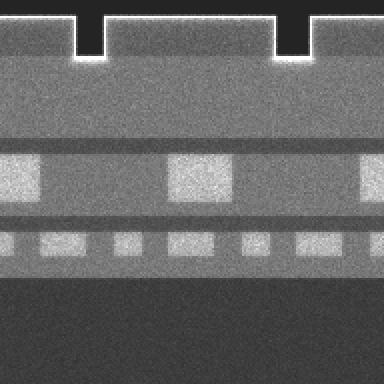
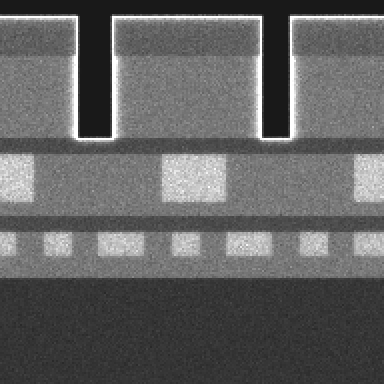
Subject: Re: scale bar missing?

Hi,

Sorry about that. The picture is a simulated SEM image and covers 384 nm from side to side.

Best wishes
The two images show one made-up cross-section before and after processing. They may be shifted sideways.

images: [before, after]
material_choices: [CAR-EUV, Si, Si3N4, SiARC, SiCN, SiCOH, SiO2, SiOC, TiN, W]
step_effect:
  removed: SiO2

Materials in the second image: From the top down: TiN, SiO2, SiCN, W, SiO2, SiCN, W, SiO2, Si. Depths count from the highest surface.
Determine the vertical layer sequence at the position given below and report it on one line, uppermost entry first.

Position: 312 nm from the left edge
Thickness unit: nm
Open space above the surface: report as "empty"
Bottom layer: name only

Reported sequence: TiN 40, SiO2 82, SiCN 16, SiO2 62, SiCN 16, W 24, SiO2 22, Si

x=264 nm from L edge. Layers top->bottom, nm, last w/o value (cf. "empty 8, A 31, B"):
empty 122, SiCN 16, SiO2 62, SiCN 16, W 24, SiO2 22, Si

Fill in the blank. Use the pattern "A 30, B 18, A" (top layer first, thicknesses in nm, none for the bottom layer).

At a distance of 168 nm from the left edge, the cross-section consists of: TiN 40, SiO2 82, SiCN 16, W 48, SiO2 14, SiCN 16, SiO2 46, Si